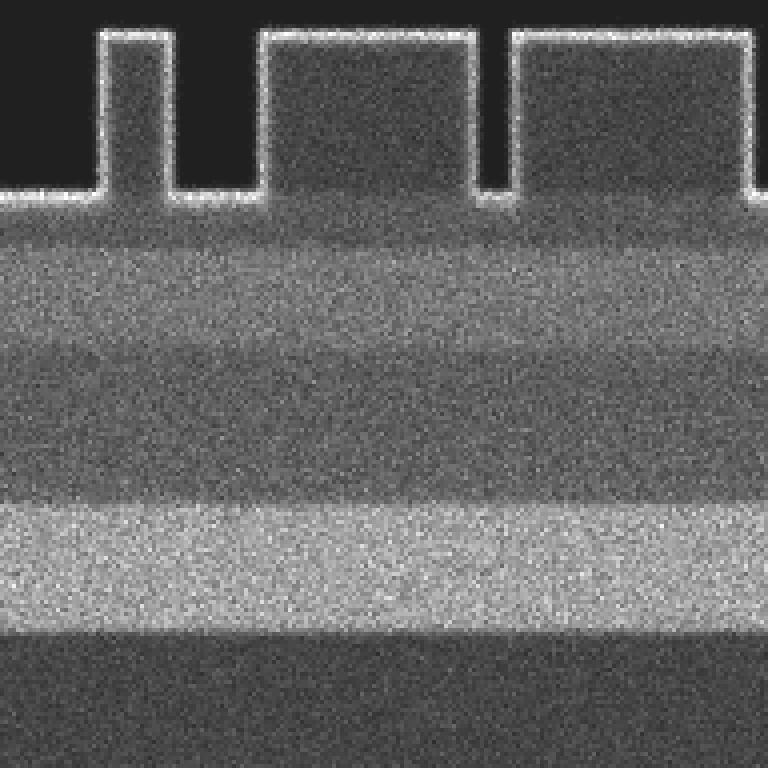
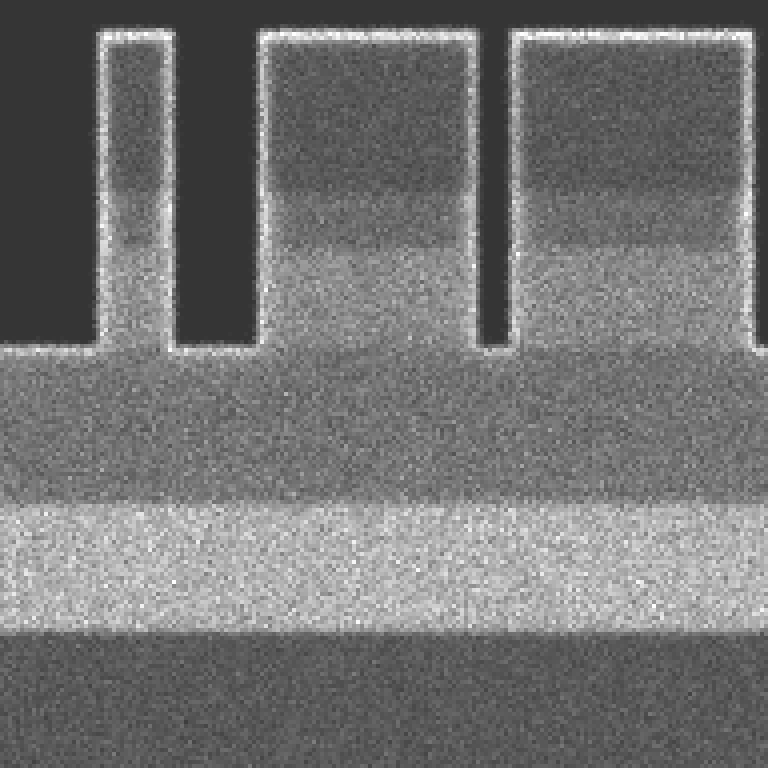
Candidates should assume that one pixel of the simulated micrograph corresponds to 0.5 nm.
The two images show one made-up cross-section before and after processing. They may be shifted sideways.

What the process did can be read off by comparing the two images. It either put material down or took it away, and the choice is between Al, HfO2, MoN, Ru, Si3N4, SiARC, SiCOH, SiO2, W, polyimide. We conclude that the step removed SiO2 and W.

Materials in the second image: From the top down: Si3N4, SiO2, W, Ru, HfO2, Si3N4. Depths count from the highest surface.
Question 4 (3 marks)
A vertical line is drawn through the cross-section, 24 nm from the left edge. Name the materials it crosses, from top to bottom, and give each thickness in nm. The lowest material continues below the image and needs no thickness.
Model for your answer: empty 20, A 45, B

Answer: empty 158, Ru 78, HfO2 64, Si3N4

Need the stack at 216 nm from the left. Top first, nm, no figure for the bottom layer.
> Si3N4 80, SiO2 28, W 50, Ru 78, HfO2 64, Si3N4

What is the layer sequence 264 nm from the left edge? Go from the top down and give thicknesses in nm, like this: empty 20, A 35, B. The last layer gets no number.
Si3N4 80, SiO2 28, W 50, Ru 78, HfO2 64, Si3N4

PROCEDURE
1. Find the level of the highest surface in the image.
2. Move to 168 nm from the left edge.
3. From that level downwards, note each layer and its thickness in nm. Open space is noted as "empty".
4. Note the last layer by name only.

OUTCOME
Si3N4 80, SiO2 28, W 50, Ru 78, HfO2 64, Si3N4